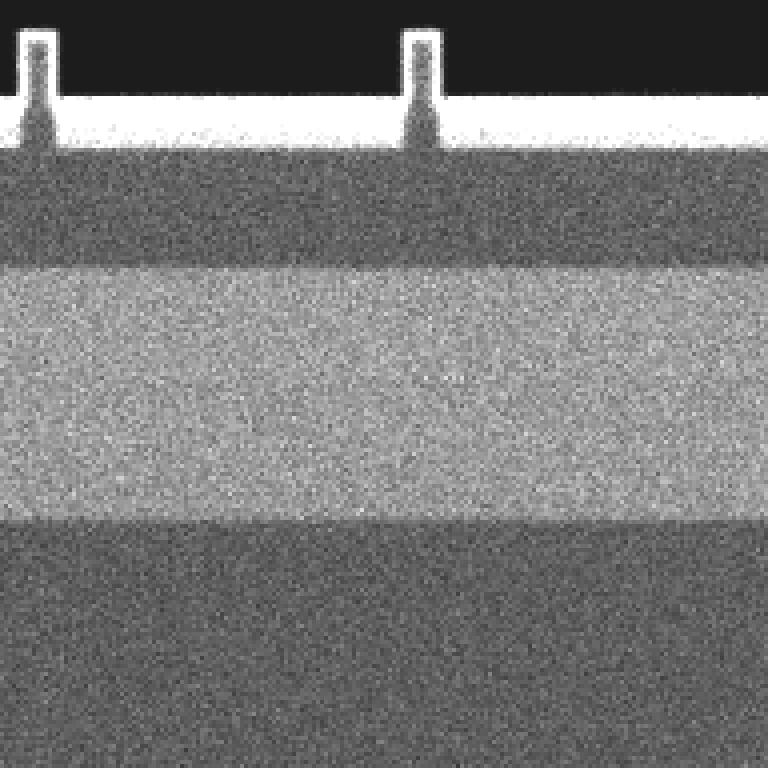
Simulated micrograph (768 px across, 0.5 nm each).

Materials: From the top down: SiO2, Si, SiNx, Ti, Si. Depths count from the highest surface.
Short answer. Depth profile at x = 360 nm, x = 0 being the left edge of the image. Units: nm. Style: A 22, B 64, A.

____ empty 34, SiO2 24, Si 60, SiNx 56, Ti 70, Si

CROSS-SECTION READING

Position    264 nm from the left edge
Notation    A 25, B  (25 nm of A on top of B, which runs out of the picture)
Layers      empty 34, SiO2 24, Si 60, SiNx 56, Ti 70, Si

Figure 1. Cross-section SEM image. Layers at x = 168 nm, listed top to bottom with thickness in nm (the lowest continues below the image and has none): empty 34, SiO2 24, Si 60, SiNx 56, Ti 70, Si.